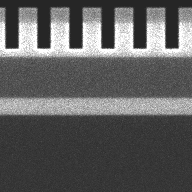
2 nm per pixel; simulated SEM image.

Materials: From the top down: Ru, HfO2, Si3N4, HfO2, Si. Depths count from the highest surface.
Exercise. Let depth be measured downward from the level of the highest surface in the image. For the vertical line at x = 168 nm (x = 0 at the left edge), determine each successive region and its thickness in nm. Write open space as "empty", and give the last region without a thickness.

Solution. Ru 30, HfO2 68, Si3N4 82, HfO2 34, Si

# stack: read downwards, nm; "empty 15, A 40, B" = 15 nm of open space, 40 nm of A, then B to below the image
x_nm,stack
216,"empty 82, HfO2 16, Si3N4 82, HfO2 34, Si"